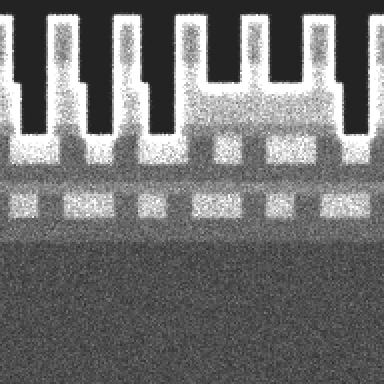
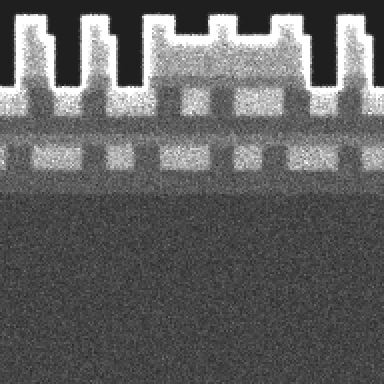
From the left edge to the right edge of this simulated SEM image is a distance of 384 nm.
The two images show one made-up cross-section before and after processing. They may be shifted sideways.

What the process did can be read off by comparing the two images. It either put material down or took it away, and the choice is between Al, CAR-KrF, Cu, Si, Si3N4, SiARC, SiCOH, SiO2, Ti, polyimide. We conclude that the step removed SiARC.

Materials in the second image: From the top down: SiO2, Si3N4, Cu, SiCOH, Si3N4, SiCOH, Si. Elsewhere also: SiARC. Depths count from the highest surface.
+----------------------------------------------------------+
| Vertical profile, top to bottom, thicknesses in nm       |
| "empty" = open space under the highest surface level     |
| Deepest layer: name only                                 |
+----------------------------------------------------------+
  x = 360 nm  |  SiO2 60, Si3N4 12, SiCOH 46, Si3N4 12, SiCOH 48, Si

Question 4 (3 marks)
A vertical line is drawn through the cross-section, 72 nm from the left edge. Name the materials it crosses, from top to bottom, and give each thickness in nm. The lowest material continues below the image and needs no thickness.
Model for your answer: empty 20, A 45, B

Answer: empty 72, Cu 28, SiCOH 18, Si3N4 12, Cu 24, SiCOH 24, Si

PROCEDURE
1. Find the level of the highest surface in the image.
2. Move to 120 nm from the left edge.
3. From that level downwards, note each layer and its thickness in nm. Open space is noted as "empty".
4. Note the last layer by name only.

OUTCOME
empty 72, Cu 28, SiCOH 18, Si3N4 12, Cu 24, SiCOH 24, Si